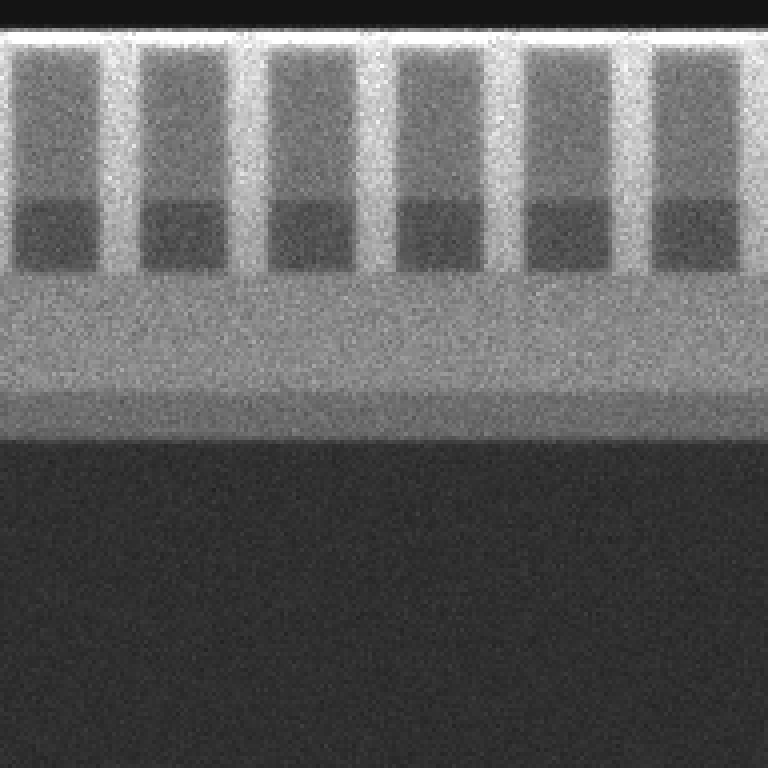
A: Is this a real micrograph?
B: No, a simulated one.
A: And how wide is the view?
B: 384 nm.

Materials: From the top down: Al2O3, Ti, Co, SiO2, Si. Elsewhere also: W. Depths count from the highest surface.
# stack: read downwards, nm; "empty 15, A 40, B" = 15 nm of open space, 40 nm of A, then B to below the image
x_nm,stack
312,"W 120, Co 60, SiO2 24, Si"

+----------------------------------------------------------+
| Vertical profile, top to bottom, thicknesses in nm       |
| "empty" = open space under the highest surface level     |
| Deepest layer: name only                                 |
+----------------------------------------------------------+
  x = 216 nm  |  Al2O3 84, Ti 36, Co 60, SiO2 24, Si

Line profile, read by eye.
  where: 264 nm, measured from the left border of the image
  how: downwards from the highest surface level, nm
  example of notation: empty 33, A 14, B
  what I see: Al2O3 84, Ti 36, Co 60, SiO2 24, Si